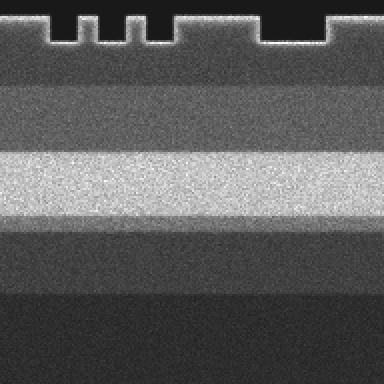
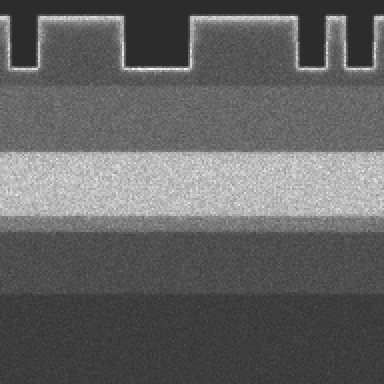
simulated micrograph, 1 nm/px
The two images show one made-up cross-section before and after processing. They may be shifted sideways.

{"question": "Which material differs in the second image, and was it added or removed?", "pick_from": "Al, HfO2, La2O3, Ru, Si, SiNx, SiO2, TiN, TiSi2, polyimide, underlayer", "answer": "TiN, removed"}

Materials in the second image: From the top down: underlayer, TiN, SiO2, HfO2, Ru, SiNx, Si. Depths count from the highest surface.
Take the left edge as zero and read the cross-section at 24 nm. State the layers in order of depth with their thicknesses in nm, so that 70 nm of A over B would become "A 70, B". empty 52, TiN 18, SiO2 66, HfO2 64, Ru 16, SiNx 62, Si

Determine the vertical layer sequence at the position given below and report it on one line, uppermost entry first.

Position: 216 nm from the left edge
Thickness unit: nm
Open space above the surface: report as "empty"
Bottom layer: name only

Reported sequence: underlayer 26, TiN 44, SiO2 66, HfO2 64, Ru 16, SiNx 62, Si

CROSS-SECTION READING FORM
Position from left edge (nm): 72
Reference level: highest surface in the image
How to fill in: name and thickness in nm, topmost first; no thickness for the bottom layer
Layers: underlayer 26, TiN 44, SiO2 66, HfO2 64, Ru 16, SiNx 62, Si